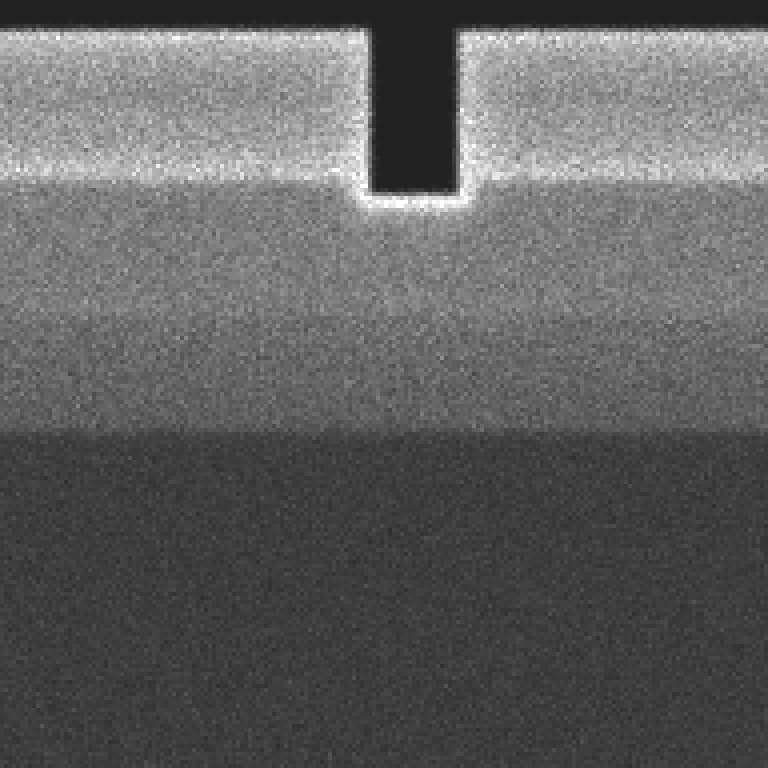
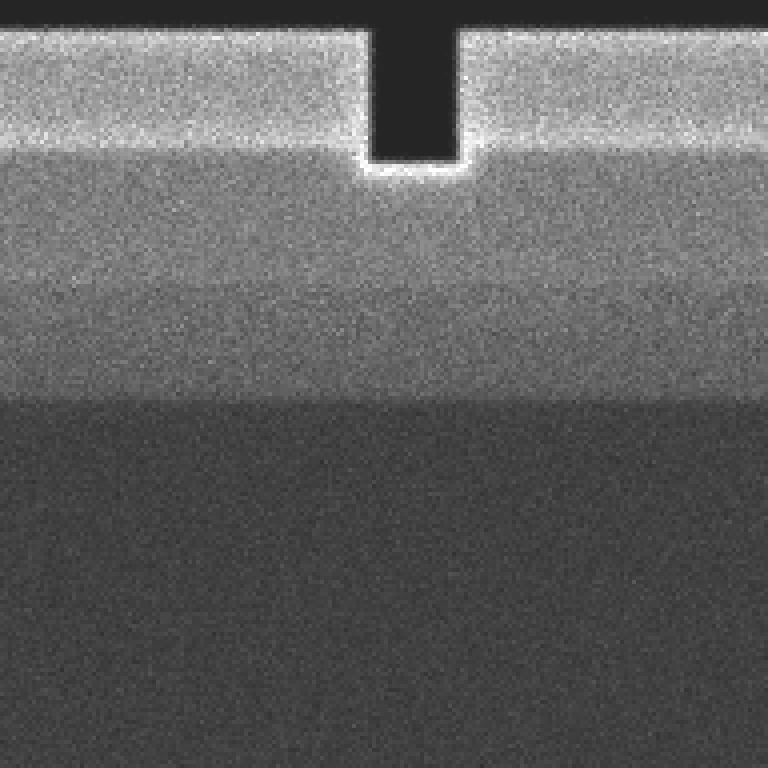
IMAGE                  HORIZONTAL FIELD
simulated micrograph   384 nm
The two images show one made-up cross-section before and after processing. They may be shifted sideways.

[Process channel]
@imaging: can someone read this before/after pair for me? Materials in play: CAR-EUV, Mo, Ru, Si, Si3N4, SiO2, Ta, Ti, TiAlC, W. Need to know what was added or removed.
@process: Ru removed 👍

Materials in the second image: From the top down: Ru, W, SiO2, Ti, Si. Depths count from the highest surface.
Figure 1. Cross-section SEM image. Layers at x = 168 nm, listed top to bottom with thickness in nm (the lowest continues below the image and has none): Ru 22, W 36, SiO2 68, Ti 58, Si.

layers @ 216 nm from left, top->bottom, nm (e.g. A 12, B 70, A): empty 66, SiO2 60, Ti 58, Si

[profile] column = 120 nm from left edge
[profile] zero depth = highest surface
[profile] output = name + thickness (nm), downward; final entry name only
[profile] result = Ru 22, W 36, SiO2 68, Ti 58, Si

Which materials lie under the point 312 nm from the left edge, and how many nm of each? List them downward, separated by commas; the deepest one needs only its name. Ru 22, W 36, SiO2 68, Ti 58, Si